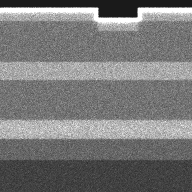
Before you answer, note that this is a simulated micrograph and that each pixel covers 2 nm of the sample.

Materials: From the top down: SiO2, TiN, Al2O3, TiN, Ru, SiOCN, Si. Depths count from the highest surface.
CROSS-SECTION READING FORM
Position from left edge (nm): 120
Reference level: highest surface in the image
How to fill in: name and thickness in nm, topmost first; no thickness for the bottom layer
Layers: SiO2 26, TiN 82, Al2O3 36, TiN 80, Ru 38, SiOCN 42, Si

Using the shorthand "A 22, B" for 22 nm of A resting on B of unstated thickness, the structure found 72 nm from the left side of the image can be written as SiO2 26, TiN 82, Al2O3 36, TiN 80, Ru 38, SiOCN 42, Si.